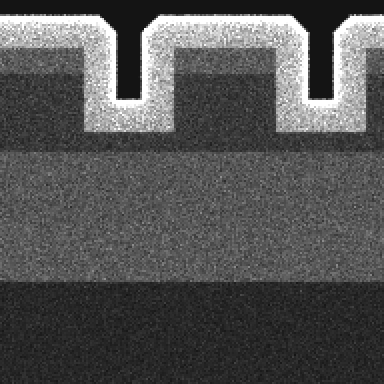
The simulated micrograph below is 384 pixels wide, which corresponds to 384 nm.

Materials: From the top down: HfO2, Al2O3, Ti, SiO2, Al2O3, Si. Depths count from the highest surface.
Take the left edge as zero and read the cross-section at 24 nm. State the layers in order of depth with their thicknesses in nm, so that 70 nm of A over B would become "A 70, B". HfO2 32, Al2O3 26, Ti 78, SiO2 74, Al2O3 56, Si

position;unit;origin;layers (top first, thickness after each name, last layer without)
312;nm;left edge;empty 84, HfO2 32, Ti 20, SiO2 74, Al2O3 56, Si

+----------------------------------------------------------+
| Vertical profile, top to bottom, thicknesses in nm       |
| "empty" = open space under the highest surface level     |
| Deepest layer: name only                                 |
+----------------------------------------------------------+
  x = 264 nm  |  HfO2 32, Al2O3 26, Ti 78, SiO2 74, Al2O3 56, Si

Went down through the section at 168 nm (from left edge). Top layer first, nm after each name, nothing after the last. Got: HfO2 116, Ti 20, SiO2 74, Al2O3 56, Si